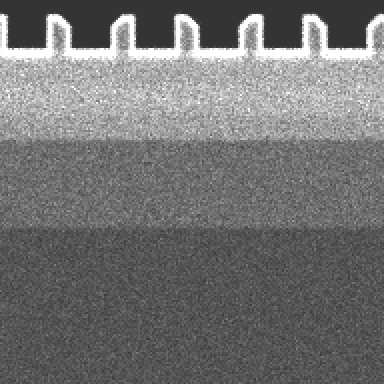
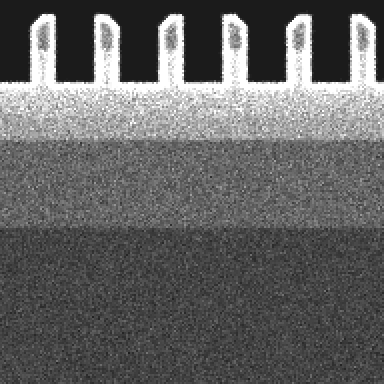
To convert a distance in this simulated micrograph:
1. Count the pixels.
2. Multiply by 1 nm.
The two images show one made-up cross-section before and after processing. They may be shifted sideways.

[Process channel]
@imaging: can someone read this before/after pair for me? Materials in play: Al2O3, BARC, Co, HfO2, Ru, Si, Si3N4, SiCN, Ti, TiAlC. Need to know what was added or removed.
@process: Al2O3 removed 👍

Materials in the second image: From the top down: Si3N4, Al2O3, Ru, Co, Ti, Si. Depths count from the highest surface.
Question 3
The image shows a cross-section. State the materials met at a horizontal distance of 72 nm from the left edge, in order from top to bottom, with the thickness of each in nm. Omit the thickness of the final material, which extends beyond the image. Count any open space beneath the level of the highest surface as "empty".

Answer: empty 68, Ru 32, Co 24, Ti 88, Si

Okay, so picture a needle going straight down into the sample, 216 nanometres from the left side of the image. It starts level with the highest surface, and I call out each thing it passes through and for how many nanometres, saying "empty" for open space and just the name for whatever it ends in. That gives empty 68, Ru 32, Co 24, Ti 88, Si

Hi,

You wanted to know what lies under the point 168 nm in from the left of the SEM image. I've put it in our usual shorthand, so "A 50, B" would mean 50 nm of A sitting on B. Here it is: empty 2, Si3N4 32, Al2O3 34, Ru 32, Co 24, Ti 88, Si